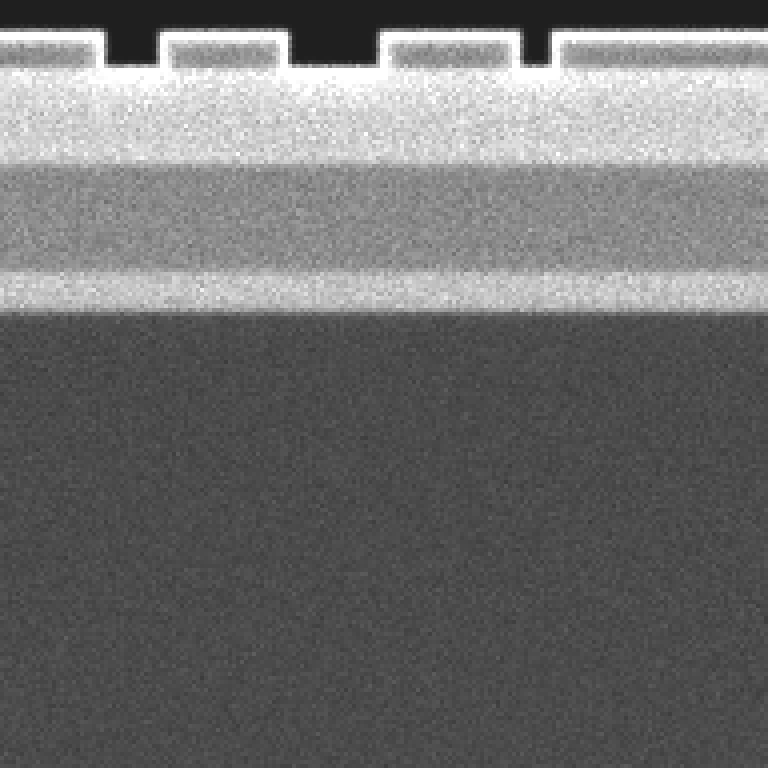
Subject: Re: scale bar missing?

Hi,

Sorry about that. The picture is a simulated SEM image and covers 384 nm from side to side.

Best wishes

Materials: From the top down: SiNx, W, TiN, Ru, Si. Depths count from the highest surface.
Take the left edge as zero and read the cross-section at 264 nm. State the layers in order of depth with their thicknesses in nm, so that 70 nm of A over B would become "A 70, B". empty 18, W 48, TiN 54, Ru 20, Si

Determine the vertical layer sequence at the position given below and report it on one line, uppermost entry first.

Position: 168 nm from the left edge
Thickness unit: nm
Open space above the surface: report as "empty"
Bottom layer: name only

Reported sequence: empty 18, W 48, TiN 54, Ru 20, Si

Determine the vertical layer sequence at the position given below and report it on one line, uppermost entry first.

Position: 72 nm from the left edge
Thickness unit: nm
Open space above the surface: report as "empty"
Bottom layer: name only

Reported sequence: empty 18, W 48, TiN 54, Ru 20, Si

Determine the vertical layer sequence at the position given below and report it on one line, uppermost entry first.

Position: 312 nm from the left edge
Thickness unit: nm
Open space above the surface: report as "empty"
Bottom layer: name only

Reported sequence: SiNx 18, W 48, TiN 54, Ru 20, Si